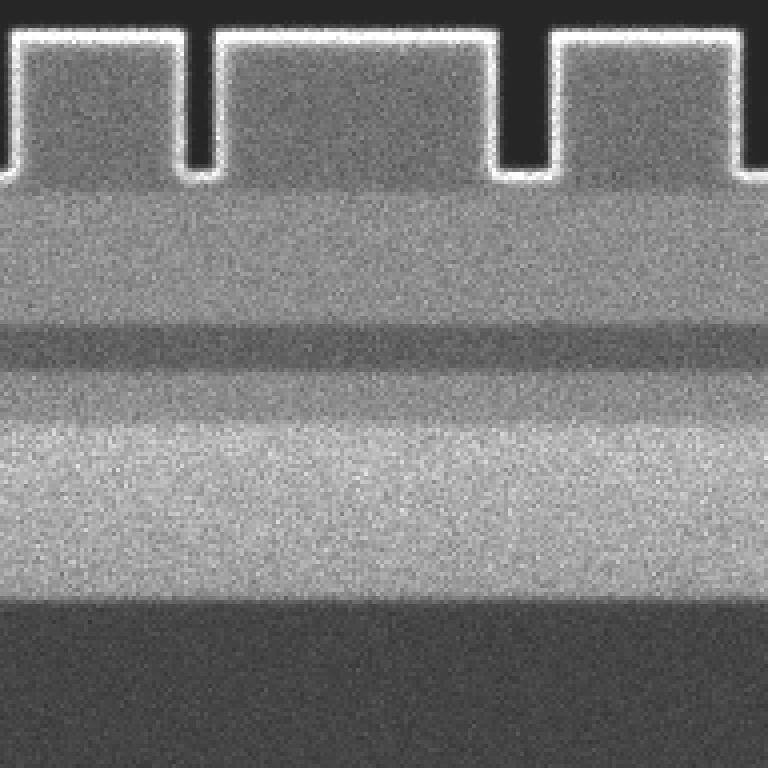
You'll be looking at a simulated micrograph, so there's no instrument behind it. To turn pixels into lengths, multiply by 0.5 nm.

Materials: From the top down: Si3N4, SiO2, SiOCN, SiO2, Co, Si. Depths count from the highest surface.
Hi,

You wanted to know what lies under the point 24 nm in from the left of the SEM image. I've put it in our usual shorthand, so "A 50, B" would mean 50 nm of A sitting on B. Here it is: Si3N4 80, SiO2 66, SiOCN 24, SiO2 26, Co 88, Si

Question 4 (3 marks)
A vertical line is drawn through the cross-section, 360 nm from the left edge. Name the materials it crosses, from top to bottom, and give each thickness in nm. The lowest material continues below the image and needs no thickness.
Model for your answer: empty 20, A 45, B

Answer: Si3N4 80, SiO2 66, SiOCN 24, SiO2 26, Co 88, Si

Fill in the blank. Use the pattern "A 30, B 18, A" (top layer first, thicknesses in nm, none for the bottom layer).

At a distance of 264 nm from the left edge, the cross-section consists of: empty 70, Si3N4 10, SiO2 66, SiOCN 24, SiO2 26, Co 88, Si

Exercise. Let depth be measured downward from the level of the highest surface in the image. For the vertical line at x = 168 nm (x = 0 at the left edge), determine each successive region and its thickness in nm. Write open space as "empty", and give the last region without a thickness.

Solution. Si3N4 80, SiO2 66, SiOCN 24, SiO2 26, Co 88, Si